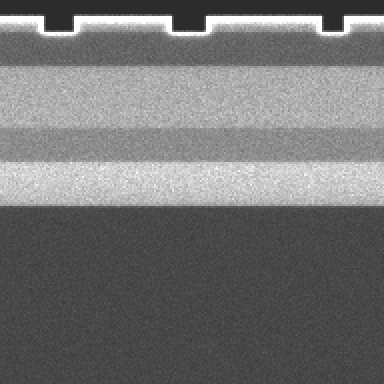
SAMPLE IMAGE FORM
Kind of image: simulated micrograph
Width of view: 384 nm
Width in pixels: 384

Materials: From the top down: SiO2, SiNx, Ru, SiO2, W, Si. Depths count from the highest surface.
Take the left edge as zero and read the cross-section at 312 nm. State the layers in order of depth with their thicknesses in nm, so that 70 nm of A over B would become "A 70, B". SiO2 16, SiNx 34, Ru 62, SiO2 34, W 44, Si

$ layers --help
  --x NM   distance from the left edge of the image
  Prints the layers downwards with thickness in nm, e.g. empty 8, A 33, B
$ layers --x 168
SiO2 16, SiNx 34, Ru 62, SiO2 34, W 44, Si